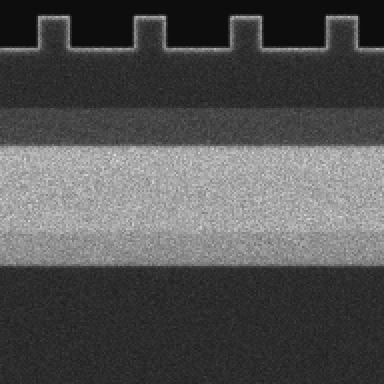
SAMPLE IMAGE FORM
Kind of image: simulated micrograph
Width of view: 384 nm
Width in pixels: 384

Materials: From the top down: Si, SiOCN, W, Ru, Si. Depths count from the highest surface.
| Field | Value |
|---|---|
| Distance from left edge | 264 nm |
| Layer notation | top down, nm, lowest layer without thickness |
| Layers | empty 32, Si 60, SiOCN 38, W 86, Ru 34, Si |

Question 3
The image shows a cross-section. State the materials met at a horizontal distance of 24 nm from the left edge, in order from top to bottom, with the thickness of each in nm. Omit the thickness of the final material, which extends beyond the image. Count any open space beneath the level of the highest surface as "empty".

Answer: empty 32, Si 60, SiOCN 38, W 86, Ru 34, Si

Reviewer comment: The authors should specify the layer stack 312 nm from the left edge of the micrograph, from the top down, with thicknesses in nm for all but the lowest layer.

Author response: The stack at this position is empty 32, Si 60, SiOCN 38, W 86, Ru 34, Si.